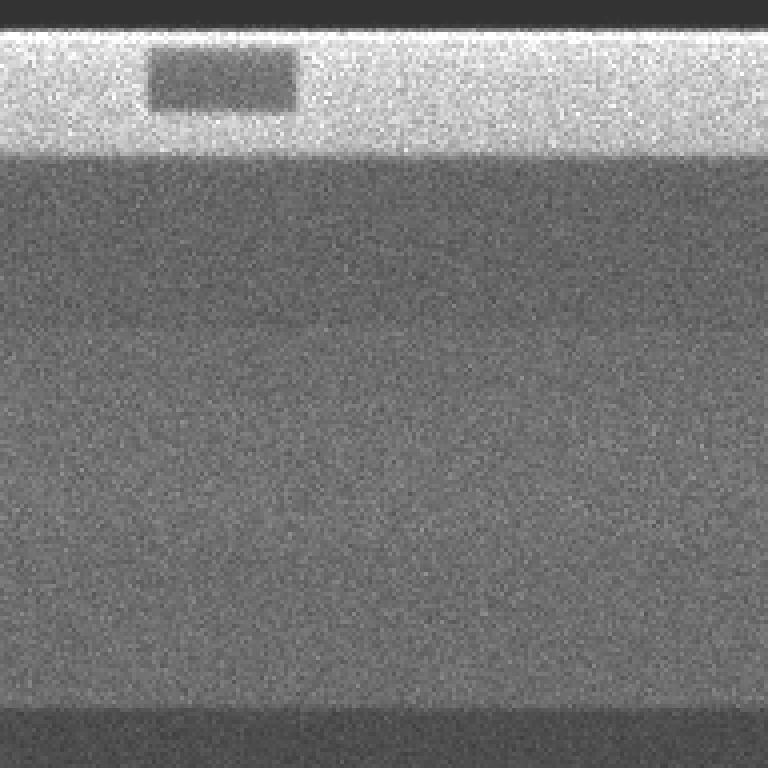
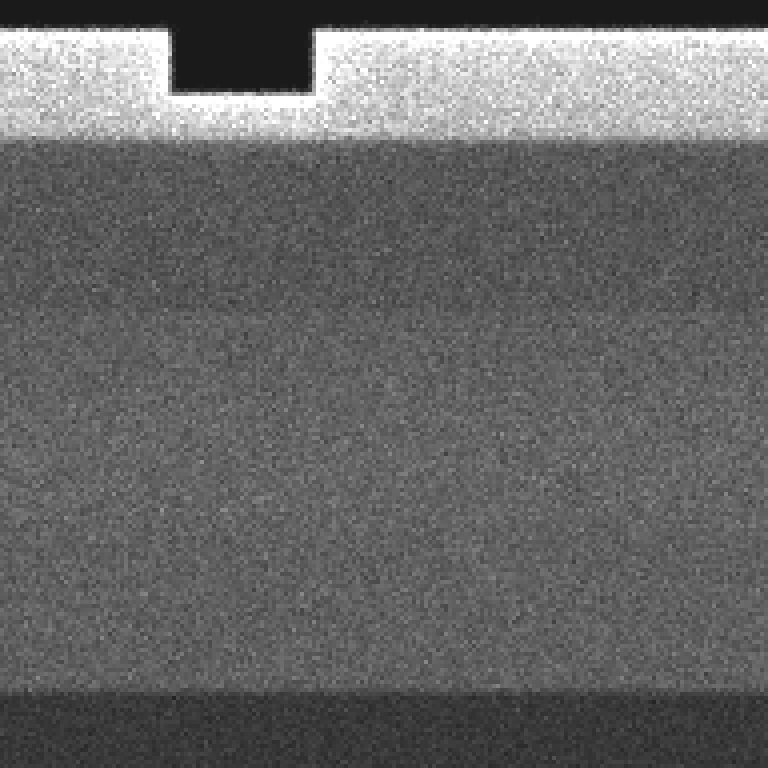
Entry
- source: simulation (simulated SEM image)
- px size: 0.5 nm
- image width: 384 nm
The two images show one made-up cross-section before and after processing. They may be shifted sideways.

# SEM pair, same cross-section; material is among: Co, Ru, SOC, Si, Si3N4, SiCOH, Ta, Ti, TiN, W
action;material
removed;SOC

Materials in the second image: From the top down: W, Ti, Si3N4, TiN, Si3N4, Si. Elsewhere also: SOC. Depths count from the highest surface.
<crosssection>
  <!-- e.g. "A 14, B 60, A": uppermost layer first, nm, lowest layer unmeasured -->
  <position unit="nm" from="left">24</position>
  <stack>W 54, Ti 86, Si3N4 34, TiN 74, Si3N4 82, Si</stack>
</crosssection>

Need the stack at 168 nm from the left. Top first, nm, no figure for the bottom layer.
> W 54, Ti 86, Si3N4 34, TiN 74, Si3N4 82, Si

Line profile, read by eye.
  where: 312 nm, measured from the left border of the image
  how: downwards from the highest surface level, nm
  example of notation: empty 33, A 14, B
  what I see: W 54, Ti 86, Si3N4 34, TiN 74, Si3N4 82, Si